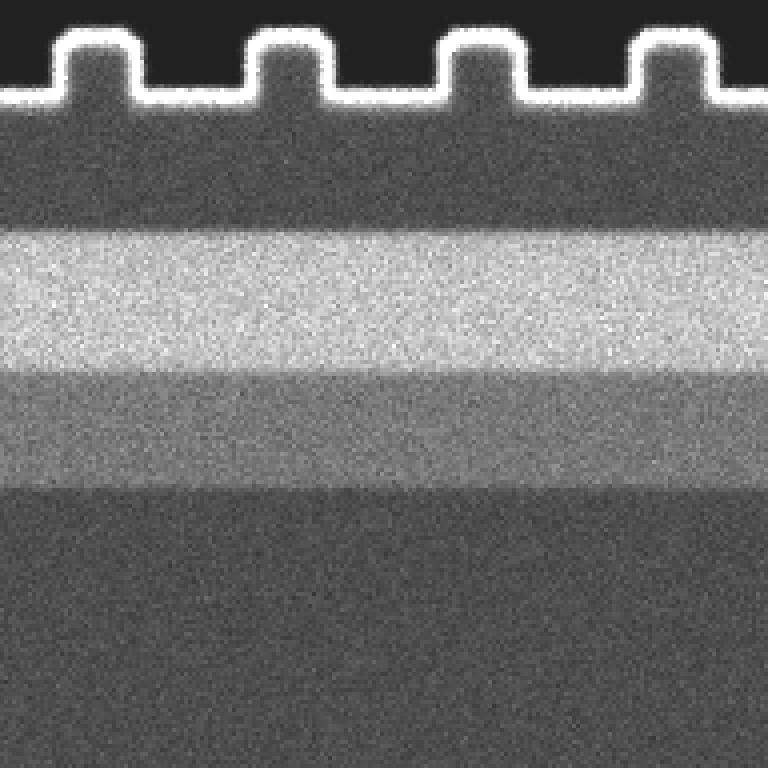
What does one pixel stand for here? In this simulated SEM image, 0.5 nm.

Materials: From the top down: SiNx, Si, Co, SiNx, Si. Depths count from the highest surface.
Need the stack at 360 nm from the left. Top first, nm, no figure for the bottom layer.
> empty 30, SiNx 10, Si 60, Co 70, SiNx 58, Si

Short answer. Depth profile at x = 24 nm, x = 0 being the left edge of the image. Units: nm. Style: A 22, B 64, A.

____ empty 30, SiNx 10, Si 60, Co 70, SiNx 58, Si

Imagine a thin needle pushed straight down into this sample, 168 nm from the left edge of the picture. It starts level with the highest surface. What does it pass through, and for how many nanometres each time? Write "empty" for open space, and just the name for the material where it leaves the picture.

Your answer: empty 30, SiNx 10, Si 60, Co 70, SiNx 58, Si